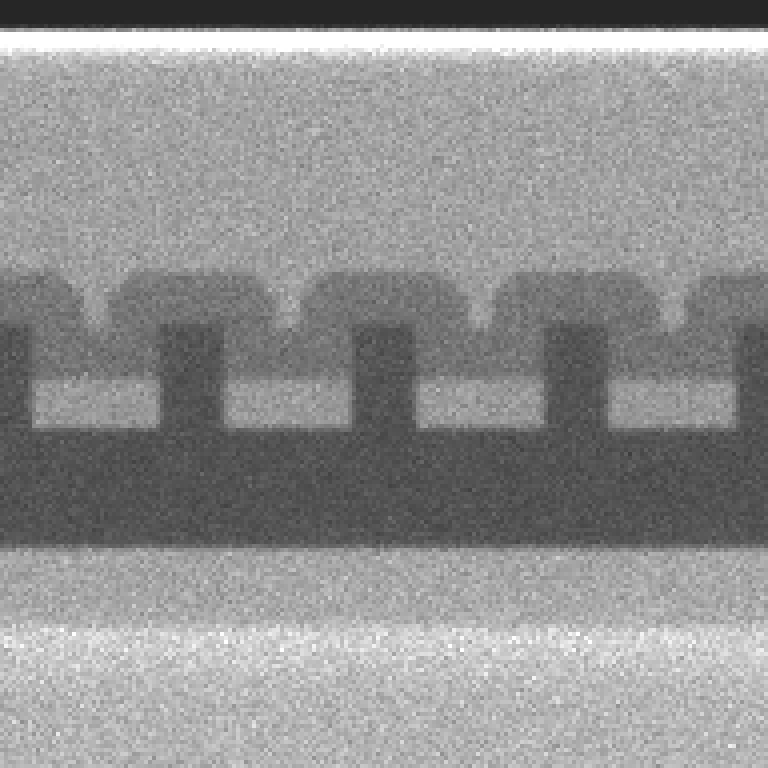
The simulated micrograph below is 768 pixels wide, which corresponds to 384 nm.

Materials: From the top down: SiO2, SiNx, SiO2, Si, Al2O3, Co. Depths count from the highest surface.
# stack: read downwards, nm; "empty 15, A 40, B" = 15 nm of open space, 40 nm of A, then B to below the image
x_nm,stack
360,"SiO2 120, SiNx 54, SiO2 24, Si 60, Al2O3 40, Co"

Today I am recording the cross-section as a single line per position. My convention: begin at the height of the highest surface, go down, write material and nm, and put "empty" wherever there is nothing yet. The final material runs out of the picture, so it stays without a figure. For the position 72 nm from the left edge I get SiO2 120, SiNx 54, SiO2 24, Si 60, Al2O3 40, Co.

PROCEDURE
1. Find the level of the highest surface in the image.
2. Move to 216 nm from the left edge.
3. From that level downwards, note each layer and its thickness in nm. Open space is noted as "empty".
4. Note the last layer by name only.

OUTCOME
SiO2 120, SiNx 54, SiO2 24, Si 60, Al2O3 40, Co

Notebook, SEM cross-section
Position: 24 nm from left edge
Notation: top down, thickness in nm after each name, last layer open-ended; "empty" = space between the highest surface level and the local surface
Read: SiO2 120, SiNx 54, SiO2 24, Si 60, Al2O3 40, Co